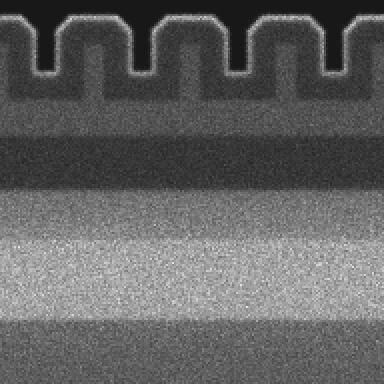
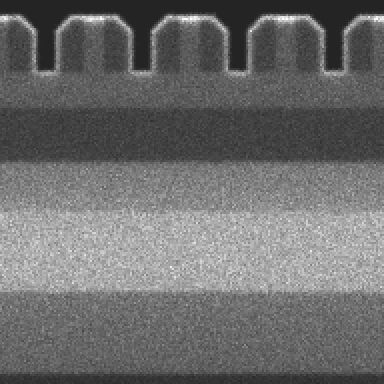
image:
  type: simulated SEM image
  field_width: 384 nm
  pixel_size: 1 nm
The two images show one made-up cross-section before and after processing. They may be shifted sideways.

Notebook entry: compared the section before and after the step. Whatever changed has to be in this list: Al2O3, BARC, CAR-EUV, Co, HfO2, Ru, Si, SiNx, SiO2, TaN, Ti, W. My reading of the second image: SiNx removed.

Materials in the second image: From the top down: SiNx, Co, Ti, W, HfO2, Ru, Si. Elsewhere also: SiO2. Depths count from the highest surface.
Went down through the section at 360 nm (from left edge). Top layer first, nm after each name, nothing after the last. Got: SiNx 56, Co 36, Ti 54, W 50, HfO2 80, Ru 82, Si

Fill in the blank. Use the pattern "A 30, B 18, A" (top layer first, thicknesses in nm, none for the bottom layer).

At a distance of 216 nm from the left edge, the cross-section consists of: empty 4, SiNx 52, Co 36, Ti 54, W 50, HfO2 80, Ru 82, Si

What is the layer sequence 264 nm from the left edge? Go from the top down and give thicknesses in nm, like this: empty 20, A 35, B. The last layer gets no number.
SiNx 56, Co 36, Ti 54, W 50, HfO2 80, Ru 82, Si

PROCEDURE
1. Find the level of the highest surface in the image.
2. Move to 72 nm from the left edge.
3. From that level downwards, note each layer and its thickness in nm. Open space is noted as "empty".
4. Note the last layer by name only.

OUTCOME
SiNx 56, Co 36, Ti 54, W 50, HfO2 80, Ru 82, Si